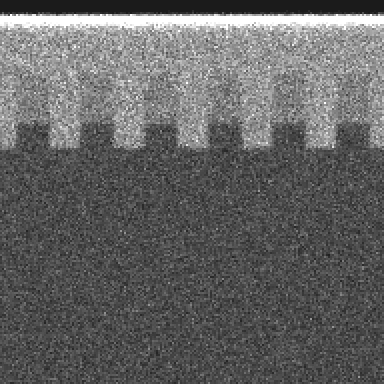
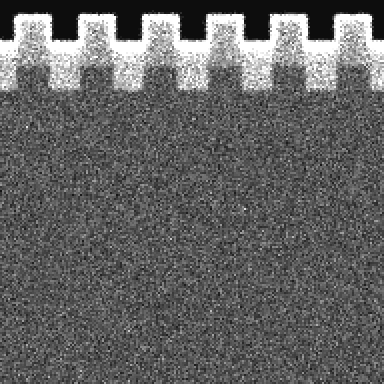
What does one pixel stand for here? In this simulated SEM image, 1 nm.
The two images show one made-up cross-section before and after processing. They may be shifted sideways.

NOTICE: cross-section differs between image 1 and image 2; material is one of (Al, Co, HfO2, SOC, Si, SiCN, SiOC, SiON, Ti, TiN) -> removed: SOC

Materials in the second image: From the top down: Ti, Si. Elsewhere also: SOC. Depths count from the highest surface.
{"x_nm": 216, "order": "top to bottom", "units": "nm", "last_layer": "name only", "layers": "Ti 50, Si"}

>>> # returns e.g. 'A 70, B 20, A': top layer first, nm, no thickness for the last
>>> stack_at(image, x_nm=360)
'Ti 50, Si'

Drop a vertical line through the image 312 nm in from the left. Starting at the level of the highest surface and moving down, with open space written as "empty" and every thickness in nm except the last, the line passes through empty 26, SOC 48, Si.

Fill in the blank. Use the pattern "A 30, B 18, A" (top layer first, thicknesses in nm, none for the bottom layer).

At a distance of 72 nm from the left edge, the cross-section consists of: empty 26, SOC 48, Si